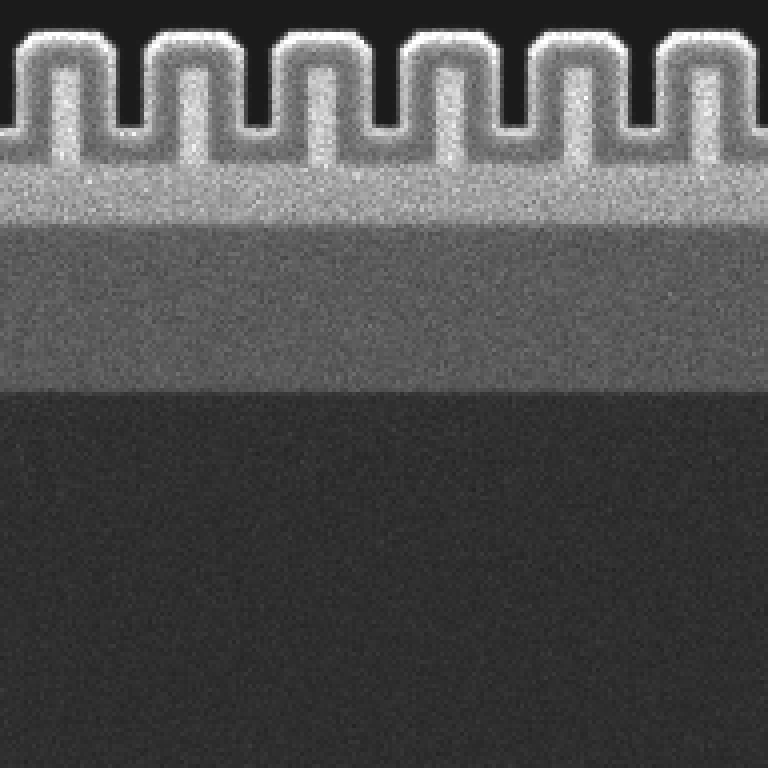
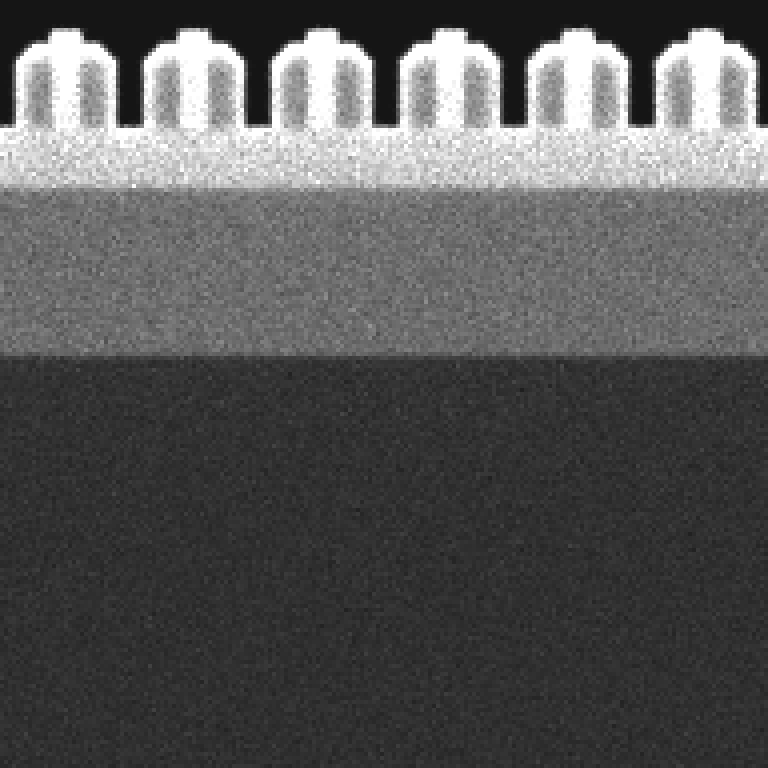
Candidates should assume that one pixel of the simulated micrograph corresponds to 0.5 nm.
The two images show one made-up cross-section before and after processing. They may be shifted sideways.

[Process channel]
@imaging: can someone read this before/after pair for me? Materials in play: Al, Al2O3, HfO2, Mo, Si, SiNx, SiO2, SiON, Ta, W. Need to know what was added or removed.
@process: Al2O3 removed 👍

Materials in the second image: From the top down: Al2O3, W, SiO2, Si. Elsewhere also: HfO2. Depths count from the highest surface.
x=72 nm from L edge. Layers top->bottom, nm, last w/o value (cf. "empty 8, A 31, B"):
empty 14, Al2O3 34, W 30, SiO2 84, Si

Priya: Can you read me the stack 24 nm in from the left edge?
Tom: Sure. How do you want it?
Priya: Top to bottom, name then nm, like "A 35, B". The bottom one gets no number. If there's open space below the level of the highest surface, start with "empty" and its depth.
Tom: empty 6, Al2O3 42, W 30, SiO2 84, Si